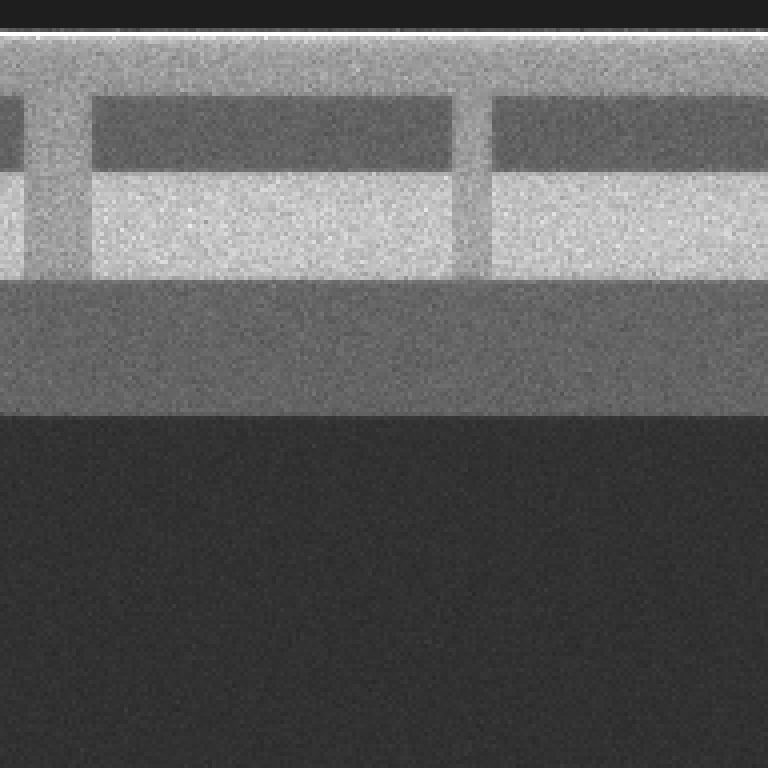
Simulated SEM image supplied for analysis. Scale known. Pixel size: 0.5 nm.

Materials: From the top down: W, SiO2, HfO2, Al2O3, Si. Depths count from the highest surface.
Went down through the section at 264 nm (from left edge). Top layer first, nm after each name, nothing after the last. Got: W 32, SiO2 38, HfO2 54, Al2O3 68, Si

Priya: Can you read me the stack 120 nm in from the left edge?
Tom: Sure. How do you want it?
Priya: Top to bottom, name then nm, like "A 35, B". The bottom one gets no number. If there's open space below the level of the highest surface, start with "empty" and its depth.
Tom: W 32, SiO2 38, HfO2 54, Al2O3 68, Si